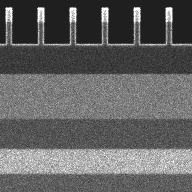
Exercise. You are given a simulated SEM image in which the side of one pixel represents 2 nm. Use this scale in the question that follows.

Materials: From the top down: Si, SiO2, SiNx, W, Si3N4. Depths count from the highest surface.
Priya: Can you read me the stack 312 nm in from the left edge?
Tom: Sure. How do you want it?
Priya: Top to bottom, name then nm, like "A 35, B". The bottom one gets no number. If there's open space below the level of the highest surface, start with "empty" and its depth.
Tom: empty 72, Si 60, SiO2 90, SiNx 60, W 50, Si3N4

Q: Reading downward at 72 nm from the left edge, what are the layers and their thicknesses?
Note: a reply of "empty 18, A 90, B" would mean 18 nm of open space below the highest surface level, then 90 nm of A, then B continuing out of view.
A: empty 72, Si 60, SiO2 90, SiNx 60, W 50, Si3N4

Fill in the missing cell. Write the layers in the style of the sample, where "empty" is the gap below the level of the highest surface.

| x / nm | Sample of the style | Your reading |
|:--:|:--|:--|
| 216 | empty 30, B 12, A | empty 72, Si 60, SiO2 90, SiNx 60, W 50, Si3N4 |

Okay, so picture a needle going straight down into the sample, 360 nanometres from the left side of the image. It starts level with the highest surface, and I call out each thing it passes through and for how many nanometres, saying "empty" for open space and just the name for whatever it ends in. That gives empty 72, Si 60, SiO2 90, SiNx 60, W 50, Si3N4